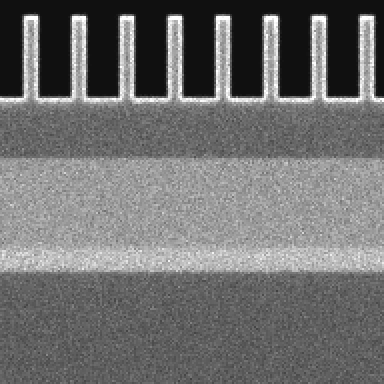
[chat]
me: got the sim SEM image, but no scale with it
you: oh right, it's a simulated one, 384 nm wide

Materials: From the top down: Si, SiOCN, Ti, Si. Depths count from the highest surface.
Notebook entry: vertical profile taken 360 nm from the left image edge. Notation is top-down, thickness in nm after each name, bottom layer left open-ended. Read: Si 142, SiOCN 90, Ti 24, Si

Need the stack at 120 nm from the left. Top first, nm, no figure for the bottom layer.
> Si 142, SiOCN 90, Ti 24, Si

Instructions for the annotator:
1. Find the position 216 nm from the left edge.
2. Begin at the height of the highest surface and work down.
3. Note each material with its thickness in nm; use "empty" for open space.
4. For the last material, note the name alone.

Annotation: Si 142, SiOCN 90, Ti 24, Si